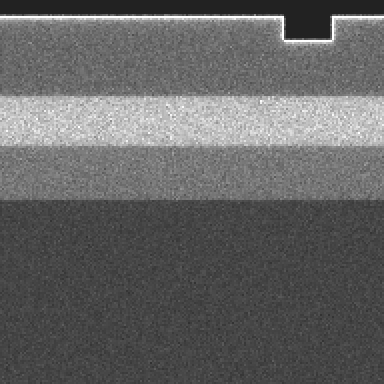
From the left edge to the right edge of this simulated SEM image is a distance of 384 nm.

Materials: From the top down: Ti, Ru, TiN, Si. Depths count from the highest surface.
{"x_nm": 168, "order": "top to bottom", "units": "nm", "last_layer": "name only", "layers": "Ti 80, Ru 50, TiN 54, Si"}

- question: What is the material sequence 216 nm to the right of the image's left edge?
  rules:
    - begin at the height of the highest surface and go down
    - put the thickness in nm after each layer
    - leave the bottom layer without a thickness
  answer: Ti 80, Ru 50, TiN 54, Si